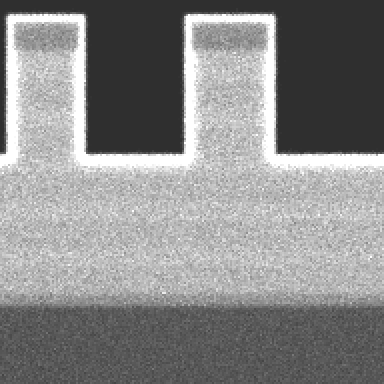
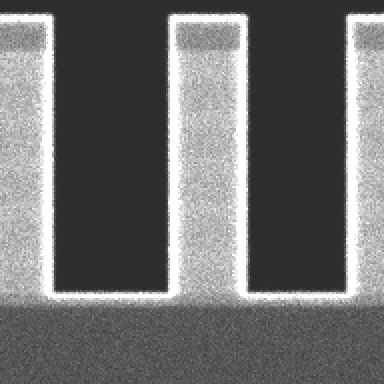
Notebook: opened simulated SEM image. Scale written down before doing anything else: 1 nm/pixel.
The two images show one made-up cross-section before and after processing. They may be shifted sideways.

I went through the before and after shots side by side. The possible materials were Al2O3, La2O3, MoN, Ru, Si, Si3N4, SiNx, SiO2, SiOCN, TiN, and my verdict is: removed, Al2O3 and SiO2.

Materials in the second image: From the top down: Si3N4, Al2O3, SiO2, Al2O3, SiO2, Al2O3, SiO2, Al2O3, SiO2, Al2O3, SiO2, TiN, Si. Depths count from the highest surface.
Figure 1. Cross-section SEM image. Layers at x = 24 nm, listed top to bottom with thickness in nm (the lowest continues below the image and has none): Si3N4 34, Al2O3 32, SiO2 28, Al2O3 18, SiO2 28, Al2O3 18, SiO2 28, Al2O3 18, SiO2 28, Al2O3 18, SiO2 28, TiN 12, Si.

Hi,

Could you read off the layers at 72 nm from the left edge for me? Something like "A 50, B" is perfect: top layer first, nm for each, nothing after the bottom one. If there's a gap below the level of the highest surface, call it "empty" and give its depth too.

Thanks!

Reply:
empty 278, TiN 12, Si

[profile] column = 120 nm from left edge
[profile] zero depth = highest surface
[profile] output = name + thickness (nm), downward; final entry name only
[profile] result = empty 278, TiN 12, Si